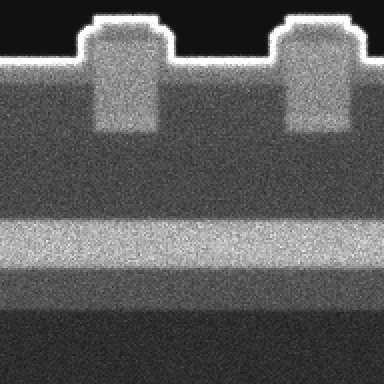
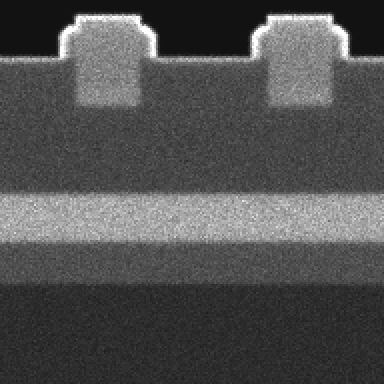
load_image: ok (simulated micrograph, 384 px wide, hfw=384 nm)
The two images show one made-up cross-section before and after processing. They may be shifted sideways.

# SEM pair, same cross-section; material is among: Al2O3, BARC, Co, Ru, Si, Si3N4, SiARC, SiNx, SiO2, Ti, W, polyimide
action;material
removed;SiO2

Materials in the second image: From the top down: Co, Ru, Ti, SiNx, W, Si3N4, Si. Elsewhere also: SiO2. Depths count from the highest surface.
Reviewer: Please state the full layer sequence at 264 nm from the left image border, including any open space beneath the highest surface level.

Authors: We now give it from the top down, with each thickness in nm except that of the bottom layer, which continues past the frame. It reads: empty 10, SiO2 32, Ti 62, SiNx 74, W 48, Si3N4 42, Si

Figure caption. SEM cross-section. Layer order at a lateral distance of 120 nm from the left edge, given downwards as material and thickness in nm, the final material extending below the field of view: Co 72, Ru 18, Ti 14, SiNx 74, W 48, Si3N4 42, Si